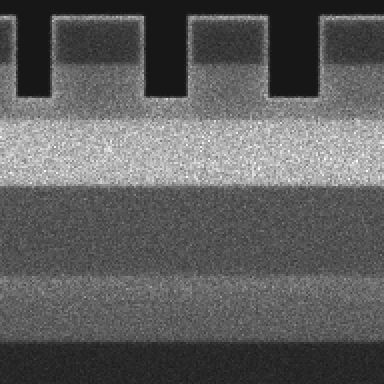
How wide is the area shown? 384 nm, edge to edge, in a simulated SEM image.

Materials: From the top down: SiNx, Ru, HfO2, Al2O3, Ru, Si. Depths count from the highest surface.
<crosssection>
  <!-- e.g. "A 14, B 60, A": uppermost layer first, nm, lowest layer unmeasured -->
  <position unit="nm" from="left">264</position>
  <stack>SiNx 48, Ru 56, HfO2 66, Al2O3 90, Ru 66, Si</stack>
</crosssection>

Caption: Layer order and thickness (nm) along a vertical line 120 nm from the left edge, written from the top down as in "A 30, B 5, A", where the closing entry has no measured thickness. SiNx 48, Ru 56, HfO2 66, Al2O3 90, Ru 66, Si